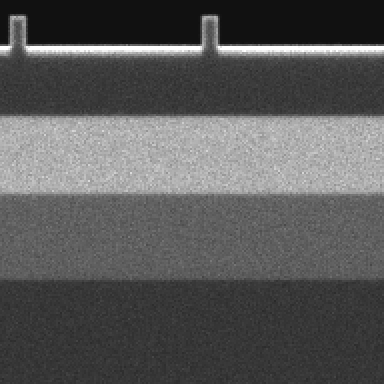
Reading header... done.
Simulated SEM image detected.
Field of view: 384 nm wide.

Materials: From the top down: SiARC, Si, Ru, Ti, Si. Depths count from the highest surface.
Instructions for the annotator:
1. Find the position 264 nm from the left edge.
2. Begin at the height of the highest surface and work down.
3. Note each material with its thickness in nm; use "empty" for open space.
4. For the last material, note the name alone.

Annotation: empty 30, SiARC 10, Si 60, Ru 78, Ti 86, Si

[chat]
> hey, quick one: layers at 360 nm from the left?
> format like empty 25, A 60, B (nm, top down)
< empty 30, SiARC 10, Si 60, Ru 78, Ti 86, Si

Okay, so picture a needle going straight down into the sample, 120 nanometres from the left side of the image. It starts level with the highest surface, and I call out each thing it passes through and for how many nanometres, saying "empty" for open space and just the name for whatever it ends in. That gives empty 30, SiARC 10, Si 60, Ru 78, Ti 86, Si